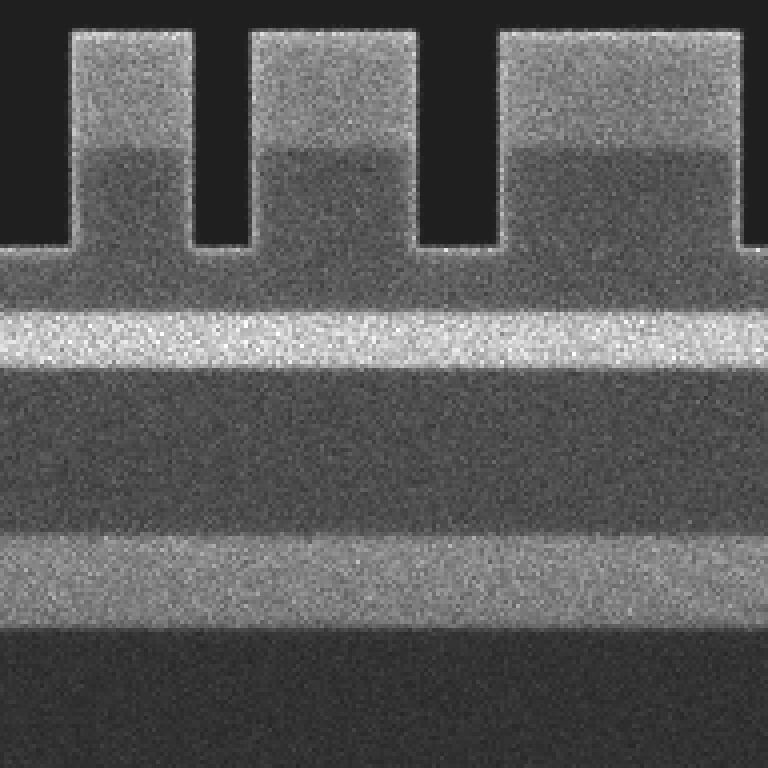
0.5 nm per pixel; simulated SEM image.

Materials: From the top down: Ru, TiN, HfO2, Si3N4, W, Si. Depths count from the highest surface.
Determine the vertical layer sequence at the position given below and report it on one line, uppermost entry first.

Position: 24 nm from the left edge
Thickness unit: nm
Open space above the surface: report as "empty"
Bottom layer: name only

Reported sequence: empty 108, TiN 32, HfO2 28, Si3N4 84, W 46, Si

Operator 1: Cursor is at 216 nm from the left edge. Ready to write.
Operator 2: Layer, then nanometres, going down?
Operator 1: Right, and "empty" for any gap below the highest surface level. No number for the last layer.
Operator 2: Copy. empty 108, TiN 32, HfO2 28, Si3N4 84, W 46, Si